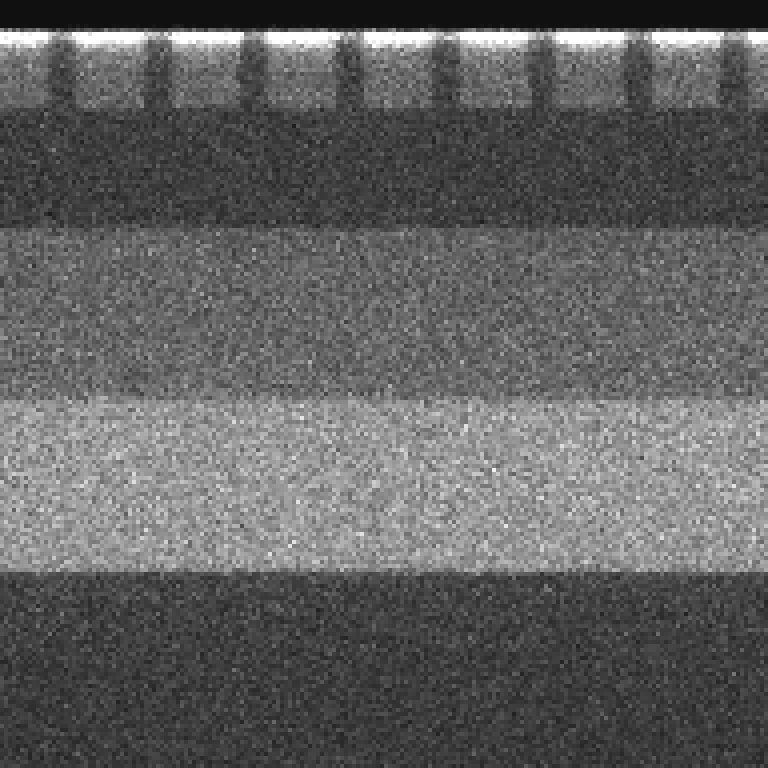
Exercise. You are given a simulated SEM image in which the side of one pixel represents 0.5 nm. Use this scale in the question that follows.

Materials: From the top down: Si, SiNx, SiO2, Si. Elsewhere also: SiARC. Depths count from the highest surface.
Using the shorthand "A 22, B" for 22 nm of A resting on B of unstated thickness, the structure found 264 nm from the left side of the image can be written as Si 98, SiNx 86, SiO2 86, Si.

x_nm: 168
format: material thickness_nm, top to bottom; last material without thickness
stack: Si 98, SiNx 86, SiO2 86, Si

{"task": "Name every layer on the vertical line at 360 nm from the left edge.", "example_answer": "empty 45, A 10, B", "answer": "Si 98, SiNx 86, SiO2 86, Si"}